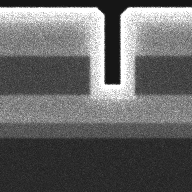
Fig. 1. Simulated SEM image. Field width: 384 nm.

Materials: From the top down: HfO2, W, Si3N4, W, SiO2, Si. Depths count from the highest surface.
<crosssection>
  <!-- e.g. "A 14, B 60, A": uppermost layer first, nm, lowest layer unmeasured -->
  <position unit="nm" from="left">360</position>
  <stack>HfO2 28, W 68, Si3N4 78, W 56, SiO2 30, Si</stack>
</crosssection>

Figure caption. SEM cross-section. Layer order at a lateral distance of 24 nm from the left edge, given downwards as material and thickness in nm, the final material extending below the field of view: HfO2 28, W 68, Si3N4 78, W 56, SiO2 30, Si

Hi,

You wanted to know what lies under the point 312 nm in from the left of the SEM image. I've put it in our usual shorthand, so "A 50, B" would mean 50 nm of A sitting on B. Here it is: HfO2 28, W 68, Si3N4 78, W 56, SiO2 30, Si